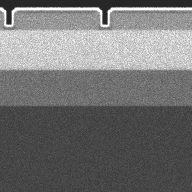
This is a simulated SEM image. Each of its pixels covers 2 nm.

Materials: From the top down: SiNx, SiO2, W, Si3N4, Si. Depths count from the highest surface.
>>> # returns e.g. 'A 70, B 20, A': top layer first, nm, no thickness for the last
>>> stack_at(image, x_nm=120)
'SiNx 10, SiO2 34, W 80, Si3N4 72, Si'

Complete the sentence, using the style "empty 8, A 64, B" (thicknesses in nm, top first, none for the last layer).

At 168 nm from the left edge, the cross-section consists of SiNx 10, SiO2 34, W 80, Si3N4 72, Si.